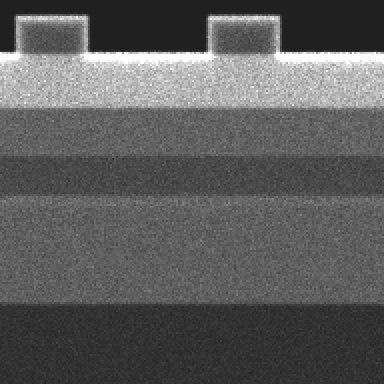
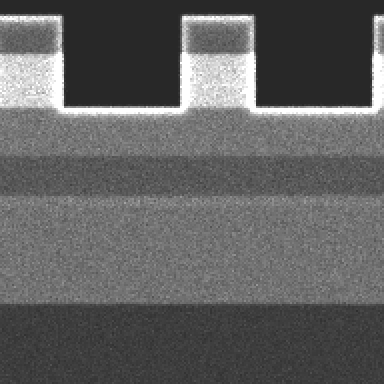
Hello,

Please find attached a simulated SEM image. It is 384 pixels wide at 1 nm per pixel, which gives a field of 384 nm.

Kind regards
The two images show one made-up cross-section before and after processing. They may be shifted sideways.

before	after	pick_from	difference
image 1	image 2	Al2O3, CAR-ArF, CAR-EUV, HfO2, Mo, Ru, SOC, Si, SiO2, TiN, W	HfO2 removed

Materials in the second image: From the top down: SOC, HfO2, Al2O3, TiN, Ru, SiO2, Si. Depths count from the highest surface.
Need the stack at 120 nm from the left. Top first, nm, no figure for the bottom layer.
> empty 92, Al2O3 48, TiN 40, Ru 10, SiO2 98, Si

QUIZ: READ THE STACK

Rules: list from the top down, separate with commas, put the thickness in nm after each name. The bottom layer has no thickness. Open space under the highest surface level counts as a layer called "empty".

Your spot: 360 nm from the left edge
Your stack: empty 92, Al2O3 48, TiN 40, Ru 10, SiO2 98, Si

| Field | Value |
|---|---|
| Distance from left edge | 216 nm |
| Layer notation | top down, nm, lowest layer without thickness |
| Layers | SOC 38, HfO2 54, Al2O3 48, TiN 40, Ru 10, SiO2 98, Si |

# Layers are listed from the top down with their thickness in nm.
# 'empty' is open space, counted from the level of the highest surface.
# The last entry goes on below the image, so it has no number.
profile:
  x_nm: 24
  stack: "SOC 38, HfO2 54, Al2O3 48, TiN 40, Ru 10, SiO2 98, Si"